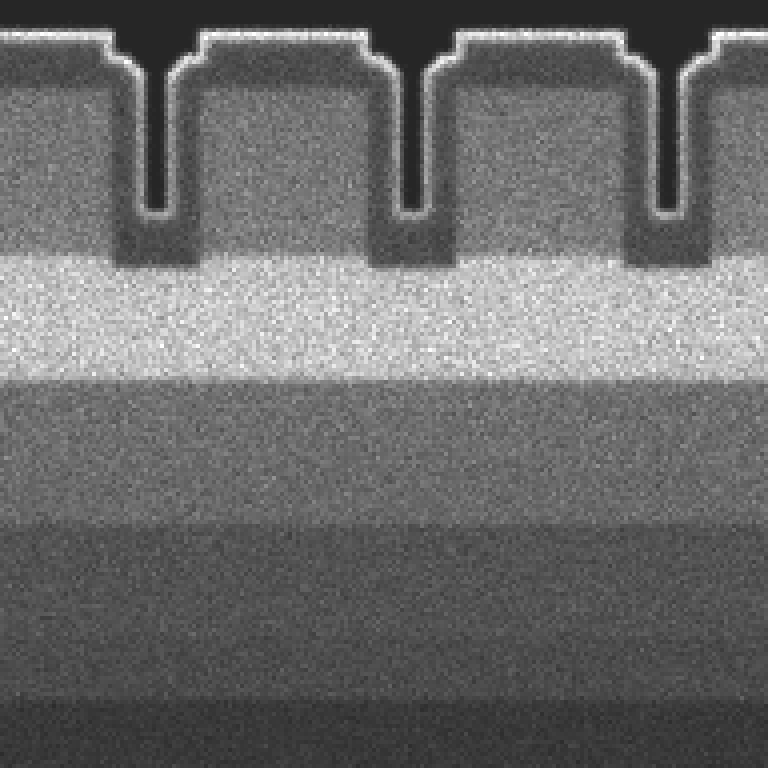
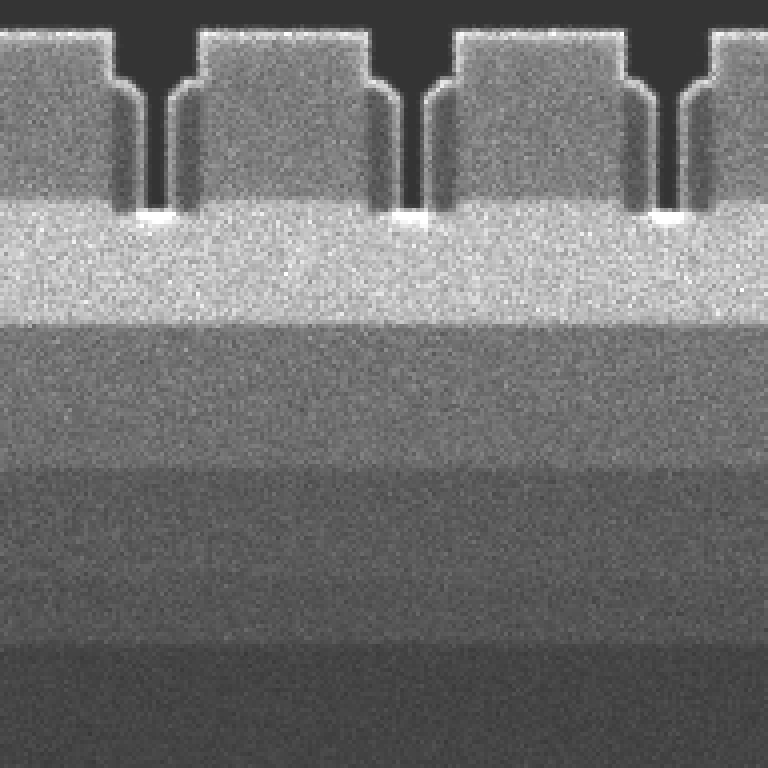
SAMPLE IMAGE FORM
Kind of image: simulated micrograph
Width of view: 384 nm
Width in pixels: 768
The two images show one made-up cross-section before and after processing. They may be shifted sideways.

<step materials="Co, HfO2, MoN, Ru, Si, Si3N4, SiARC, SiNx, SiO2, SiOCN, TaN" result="removed SiNx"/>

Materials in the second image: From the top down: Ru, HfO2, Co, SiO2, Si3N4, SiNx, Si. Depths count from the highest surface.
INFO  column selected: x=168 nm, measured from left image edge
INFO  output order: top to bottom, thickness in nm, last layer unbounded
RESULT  Ru 84, HfO2 62, Co 44, SiO2 28, Si3N4 56, SiNx 32, Si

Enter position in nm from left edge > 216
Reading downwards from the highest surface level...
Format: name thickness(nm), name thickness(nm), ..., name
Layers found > empty 28, SiNx 62, HfO2 56, Co 44, SiO2 28, Si3N4 56, SiNx 32, Si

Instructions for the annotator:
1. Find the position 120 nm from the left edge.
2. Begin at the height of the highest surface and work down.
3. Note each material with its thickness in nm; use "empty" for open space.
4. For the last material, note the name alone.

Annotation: Ru 84, HfO2 62, Co 44, SiO2 28, Si3N4 56, SiNx 32, Si